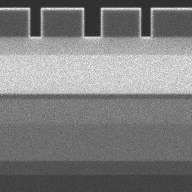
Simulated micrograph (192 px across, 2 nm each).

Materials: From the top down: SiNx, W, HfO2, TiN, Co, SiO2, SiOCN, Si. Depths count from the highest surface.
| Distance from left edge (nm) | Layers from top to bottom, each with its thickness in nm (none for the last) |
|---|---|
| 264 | SiNx 58, W 36, HfO2 78, TiN 10, Co 50, SiO2 74, SiOCN 28, Si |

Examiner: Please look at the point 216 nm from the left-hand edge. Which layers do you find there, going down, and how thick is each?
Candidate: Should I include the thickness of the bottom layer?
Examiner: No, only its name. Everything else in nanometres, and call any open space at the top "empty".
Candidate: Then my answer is SiNx 58, W 36, HfO2 78, TiN 10, Co 50, SiO2 74, SiOCN 28, Si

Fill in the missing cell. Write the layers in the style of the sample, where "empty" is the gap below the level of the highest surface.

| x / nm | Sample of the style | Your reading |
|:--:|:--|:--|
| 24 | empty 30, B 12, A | SiNx 58, W 36, HfO2 78, TiN 10, Co 50, SiO2 74, SiOCN 28, Si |